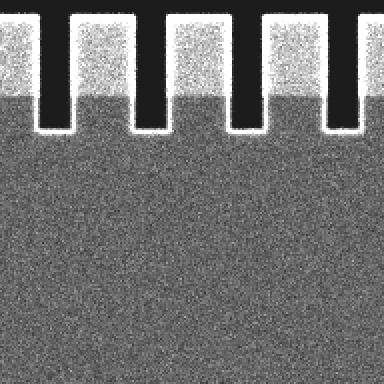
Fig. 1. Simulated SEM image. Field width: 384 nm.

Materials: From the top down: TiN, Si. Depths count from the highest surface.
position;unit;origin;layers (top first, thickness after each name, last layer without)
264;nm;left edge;TiN 80, Si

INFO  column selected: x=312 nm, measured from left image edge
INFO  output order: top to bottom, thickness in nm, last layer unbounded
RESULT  TiN 80, Si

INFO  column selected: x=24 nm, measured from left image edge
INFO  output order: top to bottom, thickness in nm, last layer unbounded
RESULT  TiN 80, Si